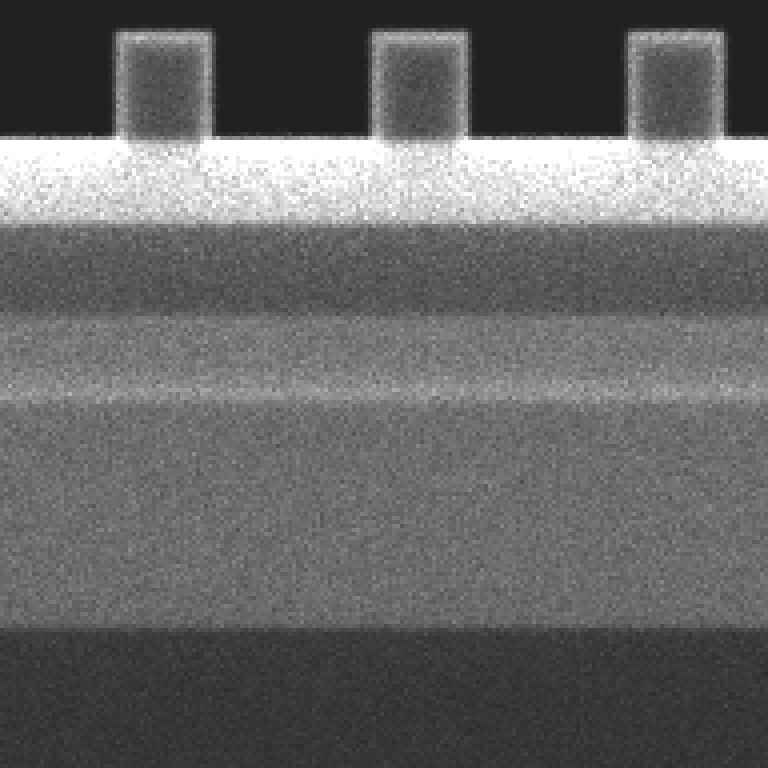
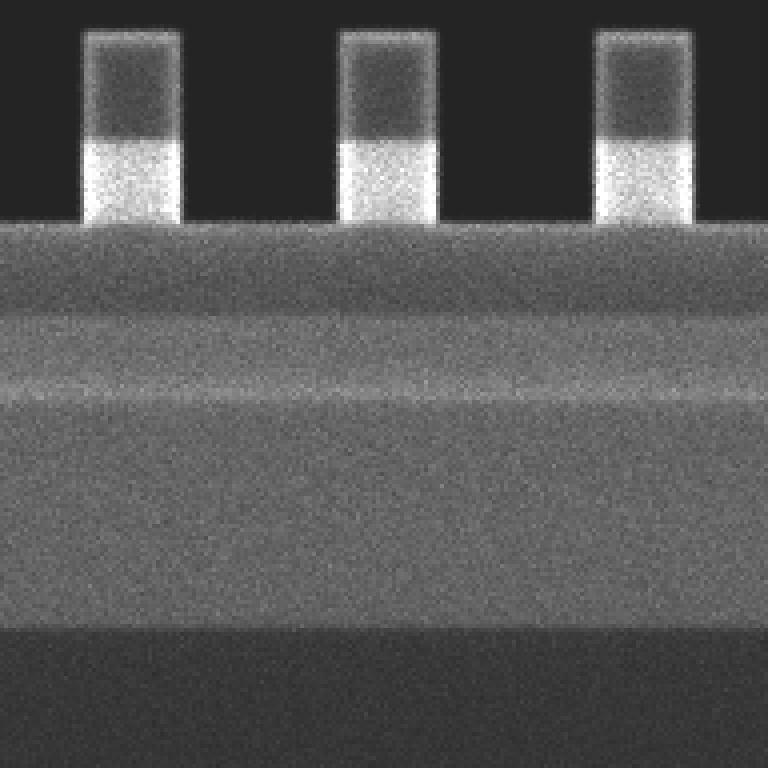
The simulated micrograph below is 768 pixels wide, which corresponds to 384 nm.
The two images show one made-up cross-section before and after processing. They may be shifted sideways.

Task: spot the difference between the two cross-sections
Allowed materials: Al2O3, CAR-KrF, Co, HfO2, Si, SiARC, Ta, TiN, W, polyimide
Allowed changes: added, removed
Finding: removed HfO2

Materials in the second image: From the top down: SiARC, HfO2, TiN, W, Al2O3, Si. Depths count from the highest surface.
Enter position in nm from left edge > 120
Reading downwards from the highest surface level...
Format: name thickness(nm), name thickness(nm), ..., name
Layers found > empty 96, TiN 46, W 42, Al2O3 114, Si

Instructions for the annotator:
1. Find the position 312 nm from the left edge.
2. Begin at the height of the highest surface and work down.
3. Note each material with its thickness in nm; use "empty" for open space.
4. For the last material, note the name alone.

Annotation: SiARC 54, HfO2 42, TiN 46, W 42, Al2O3 114, Si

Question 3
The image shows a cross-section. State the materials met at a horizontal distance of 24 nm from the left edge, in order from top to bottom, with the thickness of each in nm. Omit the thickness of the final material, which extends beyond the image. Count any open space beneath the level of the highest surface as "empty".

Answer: empty 96, TiN 46, W 42, Al2O3 114, Si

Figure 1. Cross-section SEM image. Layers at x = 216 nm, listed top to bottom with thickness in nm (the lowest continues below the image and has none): SiARC 54, HfO2 42, TiN 46, W 42, Al2O3 114, Si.